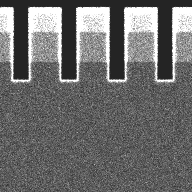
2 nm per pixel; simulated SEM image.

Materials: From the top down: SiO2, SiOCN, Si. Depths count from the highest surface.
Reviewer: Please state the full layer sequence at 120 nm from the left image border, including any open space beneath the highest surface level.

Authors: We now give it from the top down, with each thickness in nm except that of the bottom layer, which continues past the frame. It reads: SiO2 48, SiOCN 60, Si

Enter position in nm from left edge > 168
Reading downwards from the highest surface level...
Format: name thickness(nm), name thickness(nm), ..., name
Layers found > SiO2 48, SiOCN 60, Si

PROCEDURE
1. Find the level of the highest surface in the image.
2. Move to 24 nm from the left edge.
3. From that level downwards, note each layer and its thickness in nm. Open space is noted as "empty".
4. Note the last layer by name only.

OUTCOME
SiO2 48, SiOCN 60, Si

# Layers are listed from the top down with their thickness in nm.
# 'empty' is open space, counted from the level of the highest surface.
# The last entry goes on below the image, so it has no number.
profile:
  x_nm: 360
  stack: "SiO2 48, SiOCN 60, Si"